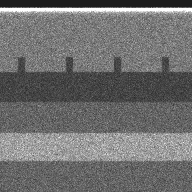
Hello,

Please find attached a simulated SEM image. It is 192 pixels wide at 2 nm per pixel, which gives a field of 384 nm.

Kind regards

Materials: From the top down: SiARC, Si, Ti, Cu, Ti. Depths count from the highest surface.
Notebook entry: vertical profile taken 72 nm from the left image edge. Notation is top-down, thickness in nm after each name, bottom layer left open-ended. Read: SiARC 128, Si 60, Ti 62, Cu 56, Ti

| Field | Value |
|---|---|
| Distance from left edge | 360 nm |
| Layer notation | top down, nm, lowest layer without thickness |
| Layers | SiARC 128, Si 60, Ti 62, Cu 56, Ti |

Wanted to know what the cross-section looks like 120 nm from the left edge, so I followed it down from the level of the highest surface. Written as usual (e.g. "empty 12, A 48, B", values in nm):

SiARC 128, Si 60, Ti 62, Cu 56, Ti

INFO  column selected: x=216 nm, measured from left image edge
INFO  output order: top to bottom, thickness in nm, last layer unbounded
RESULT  SiARC 128, Si 60, Ti 62, Cu 56, Ti